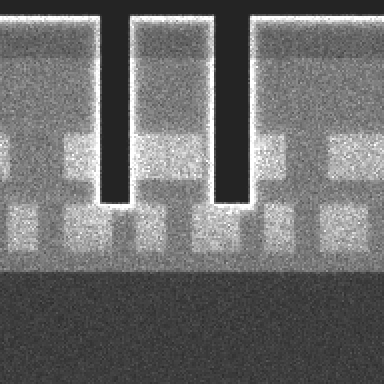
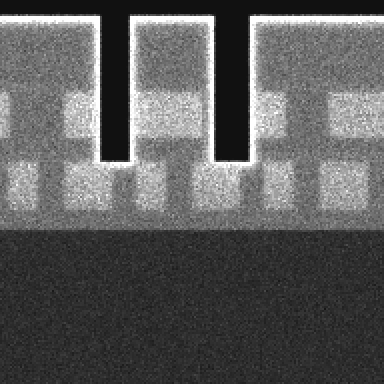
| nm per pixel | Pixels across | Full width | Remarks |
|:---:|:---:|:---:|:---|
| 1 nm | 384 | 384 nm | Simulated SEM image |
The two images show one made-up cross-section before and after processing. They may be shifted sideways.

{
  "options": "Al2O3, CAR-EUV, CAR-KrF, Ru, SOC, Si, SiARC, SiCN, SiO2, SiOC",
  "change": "removed",
  "material": "SOC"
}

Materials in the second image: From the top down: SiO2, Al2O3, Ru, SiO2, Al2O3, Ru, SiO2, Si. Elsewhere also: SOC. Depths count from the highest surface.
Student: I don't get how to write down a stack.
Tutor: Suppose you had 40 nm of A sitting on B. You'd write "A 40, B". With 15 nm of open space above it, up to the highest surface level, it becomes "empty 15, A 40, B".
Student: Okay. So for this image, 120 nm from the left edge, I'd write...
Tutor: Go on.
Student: empty 146, SiO2 68, Si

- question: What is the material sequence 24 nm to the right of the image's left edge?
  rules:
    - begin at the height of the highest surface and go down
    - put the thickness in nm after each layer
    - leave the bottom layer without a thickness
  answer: SiO2 66, Al2O3 10, SiO2 60, Al2O3 10, Ru 48, SiO2 20, Si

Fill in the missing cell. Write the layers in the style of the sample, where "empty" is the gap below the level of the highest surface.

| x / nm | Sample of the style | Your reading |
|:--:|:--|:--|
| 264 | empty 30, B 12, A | SiO2 66, Al2O3 10, Ru 46, SiO2 14, Al2O3 10, Ru 48, SiO2 20, Si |